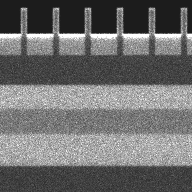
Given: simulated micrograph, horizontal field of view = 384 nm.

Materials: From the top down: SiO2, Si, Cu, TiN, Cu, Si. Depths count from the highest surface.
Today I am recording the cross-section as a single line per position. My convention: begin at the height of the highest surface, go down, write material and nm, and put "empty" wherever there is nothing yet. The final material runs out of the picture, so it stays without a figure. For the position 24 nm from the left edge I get empty 52, SiO2 42, Si 60, Cu 48, TiN 50, Cu 64, Si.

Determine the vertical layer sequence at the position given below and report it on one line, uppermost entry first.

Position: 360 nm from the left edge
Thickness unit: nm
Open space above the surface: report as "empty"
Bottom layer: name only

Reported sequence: empty 52, SiO2 42, Si 60, Cu 48, TiN 50, Cu 64, Si